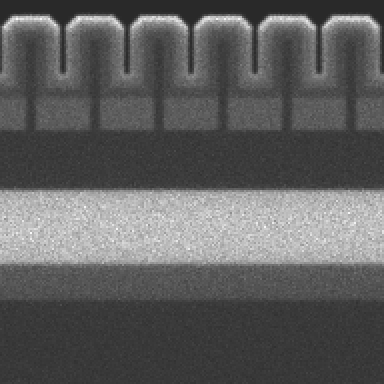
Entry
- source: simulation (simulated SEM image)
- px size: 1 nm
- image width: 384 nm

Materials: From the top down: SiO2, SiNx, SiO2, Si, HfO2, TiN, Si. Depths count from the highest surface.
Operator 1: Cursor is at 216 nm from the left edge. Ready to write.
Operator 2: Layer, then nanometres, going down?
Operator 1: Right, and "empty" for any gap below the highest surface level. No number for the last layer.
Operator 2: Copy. SiO2 14, SiNx 68, SiO2 32, Si 60, HfO2 74, TiN 36, Si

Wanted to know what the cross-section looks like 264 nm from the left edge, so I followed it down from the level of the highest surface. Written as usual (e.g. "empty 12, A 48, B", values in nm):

empty 4, SiO2 68, SiNx 10, SiO2 32, Si 60, HfO2 74, TiN 36, Si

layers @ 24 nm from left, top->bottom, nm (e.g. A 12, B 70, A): SiO2 14, SiNx 68, SiO2 32, Si 60, HfO2 74, TiN 36, Si